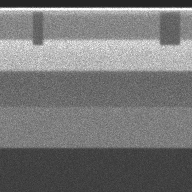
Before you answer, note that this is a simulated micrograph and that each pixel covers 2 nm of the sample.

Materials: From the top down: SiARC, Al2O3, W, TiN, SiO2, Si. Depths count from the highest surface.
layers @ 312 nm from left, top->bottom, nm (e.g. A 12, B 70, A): SiARC 8, Al2O3 56, W 62, TiN 72, SiO2 82, Si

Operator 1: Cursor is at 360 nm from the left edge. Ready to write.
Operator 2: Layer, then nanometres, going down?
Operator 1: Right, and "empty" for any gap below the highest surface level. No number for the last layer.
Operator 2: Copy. SiARC 8, Al2O3 56, W 62, TiN 72, SiO2 82, Si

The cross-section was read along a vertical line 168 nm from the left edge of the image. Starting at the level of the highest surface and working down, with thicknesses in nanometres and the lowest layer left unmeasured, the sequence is SiARC 8, Al2O3 56, W 62, TiN 72, SiO2 82, Si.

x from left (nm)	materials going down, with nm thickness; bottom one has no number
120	SiARC 8, Al2O3 56, W 62, TiN 72, SiO2 82, Si